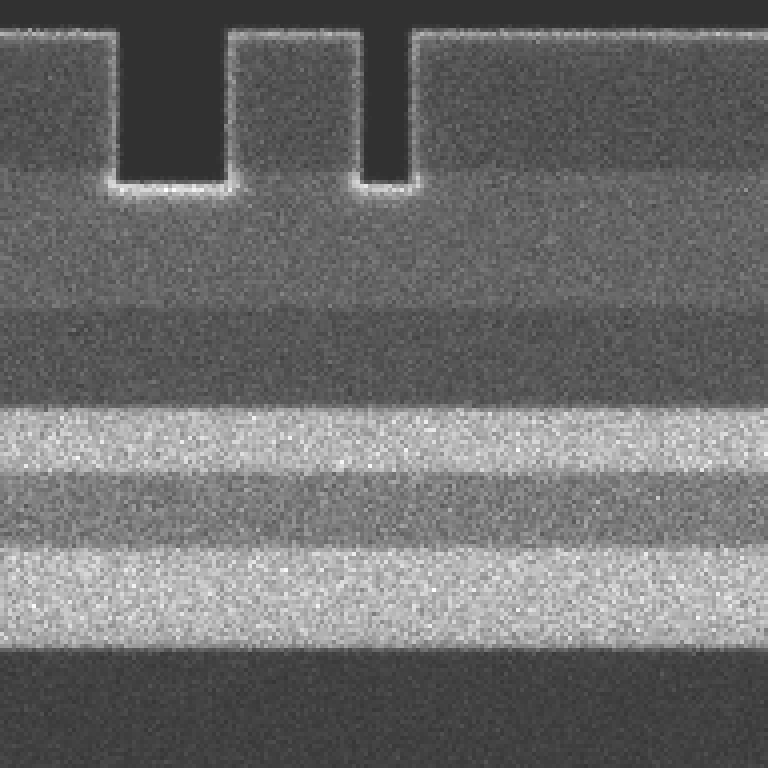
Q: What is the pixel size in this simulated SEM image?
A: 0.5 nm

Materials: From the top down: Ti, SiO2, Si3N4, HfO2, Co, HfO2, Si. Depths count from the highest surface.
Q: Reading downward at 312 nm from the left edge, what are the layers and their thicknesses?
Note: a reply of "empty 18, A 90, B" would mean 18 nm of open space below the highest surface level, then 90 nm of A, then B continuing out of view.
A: Ti 70, SiO2 68, Si3N4 50, HfO2 32, Co 38, HfO2 50, Si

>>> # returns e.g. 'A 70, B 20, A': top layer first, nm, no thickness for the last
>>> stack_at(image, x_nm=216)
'Ti 70, SiO2 68, Si3N4 50, HfO2 32, Co 38, HfO2 50, Si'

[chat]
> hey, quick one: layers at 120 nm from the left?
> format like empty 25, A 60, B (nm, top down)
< Ti 70, SiO2 68, Si3N4 50, HfO2 32, Co 38, HfO2 50, Si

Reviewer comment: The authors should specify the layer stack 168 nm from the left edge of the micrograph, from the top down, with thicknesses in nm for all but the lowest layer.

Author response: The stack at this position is Ti 70, SiO2 68, Si3N4 50, HfO2 32, Co 38, HfO2 50, Si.